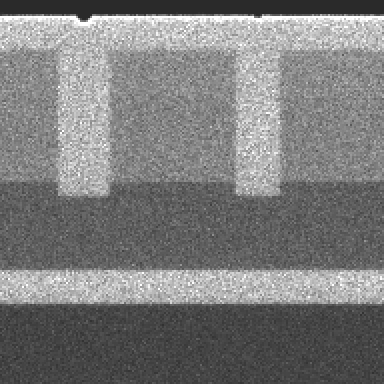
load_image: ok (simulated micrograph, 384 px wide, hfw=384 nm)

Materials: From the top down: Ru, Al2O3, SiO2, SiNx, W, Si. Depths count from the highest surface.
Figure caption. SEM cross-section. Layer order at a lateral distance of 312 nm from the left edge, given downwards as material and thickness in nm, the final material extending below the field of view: Ru 34, Al2O3 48, SiO2 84, SiNx 88, W 34, Si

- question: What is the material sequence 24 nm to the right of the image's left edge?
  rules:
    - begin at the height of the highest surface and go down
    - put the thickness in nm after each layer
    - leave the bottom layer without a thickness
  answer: Ru 34, Al2O3 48, SiO2 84, SiNx 88, W 34, Si